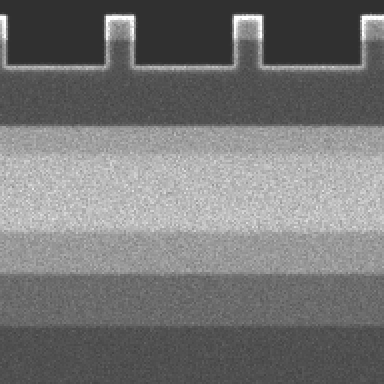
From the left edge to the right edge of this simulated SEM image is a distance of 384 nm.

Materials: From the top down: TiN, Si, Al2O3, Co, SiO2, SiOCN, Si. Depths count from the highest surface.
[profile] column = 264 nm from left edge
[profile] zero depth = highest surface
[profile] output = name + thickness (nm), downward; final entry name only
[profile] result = empty 50, Si 60, Al2O3 28, Co 78, SiO2 42, SiOCN 52, Si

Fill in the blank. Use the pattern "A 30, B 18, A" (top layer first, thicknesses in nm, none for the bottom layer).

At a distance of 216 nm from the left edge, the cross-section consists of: empty 50, Si 60, Al2O3 28, Co 78, SiO2 42, SiOCN 52, Si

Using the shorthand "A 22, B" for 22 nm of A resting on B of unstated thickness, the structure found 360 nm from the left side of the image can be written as empty 50, Si 60, Al2O3 28, Co 78, SiO2 42, SiOCN 52, Si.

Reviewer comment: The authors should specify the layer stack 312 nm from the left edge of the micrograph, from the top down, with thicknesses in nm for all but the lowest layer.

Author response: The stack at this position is empty 50, Si 60, Al2O3 28, Co 78, SiO2 42, SiOCN 52, Si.